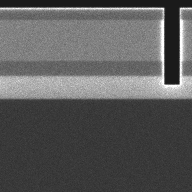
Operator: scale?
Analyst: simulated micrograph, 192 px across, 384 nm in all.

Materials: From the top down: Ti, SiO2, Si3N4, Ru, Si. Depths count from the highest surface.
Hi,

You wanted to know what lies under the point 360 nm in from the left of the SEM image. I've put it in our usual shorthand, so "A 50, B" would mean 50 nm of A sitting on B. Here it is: Ti 24, SiO2 82, Si3N4 30, Ru 46, Si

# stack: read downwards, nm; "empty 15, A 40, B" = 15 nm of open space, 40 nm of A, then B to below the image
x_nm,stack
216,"Ti 24, SiO2 82, Si3N4 30, Ru 46, Si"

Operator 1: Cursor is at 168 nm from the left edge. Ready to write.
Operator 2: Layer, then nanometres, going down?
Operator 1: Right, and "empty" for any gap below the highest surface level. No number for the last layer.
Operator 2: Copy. Ti 24, SiO2 82, Si3N4 30, Ru 46, Si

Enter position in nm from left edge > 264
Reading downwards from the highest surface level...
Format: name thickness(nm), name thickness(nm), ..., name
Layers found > Ti 24, SiO2 82, Si3N4 30, Ru 46, Si